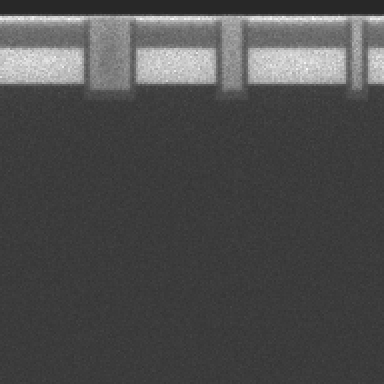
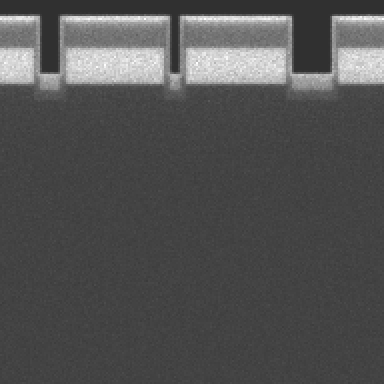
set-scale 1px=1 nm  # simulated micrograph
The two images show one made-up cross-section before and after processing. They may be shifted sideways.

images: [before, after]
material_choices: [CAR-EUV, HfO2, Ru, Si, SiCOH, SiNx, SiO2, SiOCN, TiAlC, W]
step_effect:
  removed: W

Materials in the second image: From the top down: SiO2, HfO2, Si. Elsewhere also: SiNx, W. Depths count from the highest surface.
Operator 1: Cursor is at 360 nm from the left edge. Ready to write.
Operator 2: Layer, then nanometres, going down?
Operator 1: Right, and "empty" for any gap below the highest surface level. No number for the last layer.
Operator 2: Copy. SiO2 32, HfO2 36, Si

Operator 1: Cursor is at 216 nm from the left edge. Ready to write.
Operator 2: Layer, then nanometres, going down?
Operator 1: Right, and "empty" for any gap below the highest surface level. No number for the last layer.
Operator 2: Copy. SiO2 32, HfO2 36, Si